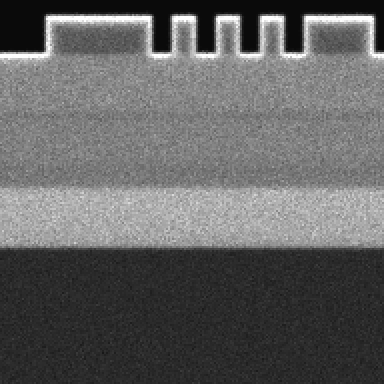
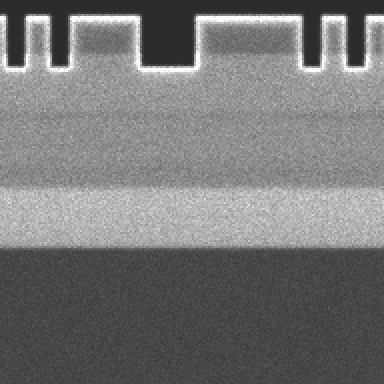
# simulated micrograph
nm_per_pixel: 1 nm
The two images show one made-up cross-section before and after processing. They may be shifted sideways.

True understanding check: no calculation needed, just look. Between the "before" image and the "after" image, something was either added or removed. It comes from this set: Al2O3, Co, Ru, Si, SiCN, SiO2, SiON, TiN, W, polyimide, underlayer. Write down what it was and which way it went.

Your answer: Ru (removed)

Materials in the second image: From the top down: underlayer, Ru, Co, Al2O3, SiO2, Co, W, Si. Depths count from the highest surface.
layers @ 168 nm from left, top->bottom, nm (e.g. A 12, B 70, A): empty 52, Ru 44, Co 8, Al2O3 38, SiO2 8, Co 22, W 60, Si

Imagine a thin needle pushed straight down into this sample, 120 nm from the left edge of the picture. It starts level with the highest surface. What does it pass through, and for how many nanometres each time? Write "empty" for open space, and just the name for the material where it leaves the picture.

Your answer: underlayer 38, Ru 58, Co 8, Al2O3 38, SiO2 8, Co 22, W 60, Si